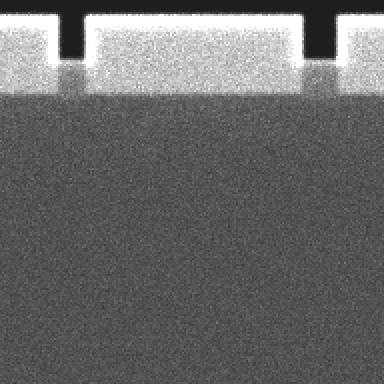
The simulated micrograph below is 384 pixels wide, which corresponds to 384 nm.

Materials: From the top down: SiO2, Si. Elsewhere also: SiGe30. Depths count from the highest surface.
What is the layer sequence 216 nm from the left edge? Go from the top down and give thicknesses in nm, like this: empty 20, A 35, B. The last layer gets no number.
SiO2 78, Si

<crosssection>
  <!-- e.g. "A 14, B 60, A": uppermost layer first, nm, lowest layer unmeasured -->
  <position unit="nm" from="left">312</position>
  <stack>empty 44, SiGe30 40, Si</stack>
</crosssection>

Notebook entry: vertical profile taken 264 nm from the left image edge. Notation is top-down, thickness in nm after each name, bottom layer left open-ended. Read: SiO2 78, Si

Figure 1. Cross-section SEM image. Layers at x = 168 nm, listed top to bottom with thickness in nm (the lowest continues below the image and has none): SiO2 78, Si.